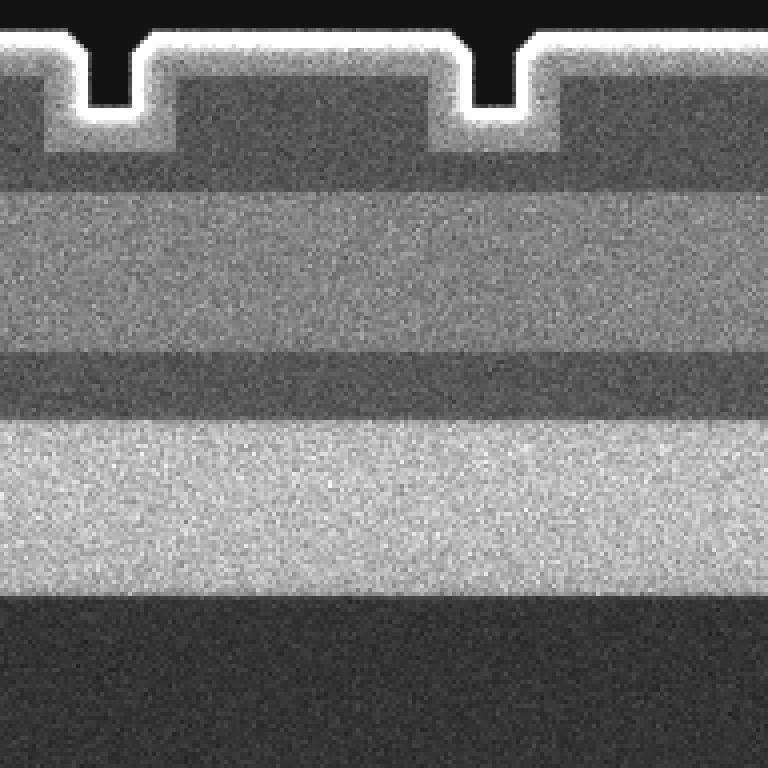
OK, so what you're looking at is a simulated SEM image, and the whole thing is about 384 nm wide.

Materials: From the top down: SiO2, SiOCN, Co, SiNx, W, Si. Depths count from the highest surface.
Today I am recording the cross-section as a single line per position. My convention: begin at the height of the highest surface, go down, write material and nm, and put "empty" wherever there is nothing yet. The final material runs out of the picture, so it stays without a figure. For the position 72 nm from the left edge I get empty 4, SiO2 56, SiOCN 20, Co 80, SiNx 34, W 88, Si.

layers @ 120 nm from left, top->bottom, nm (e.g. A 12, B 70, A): SiO2 22, SiOCN 58, Co 80, SiNx 34, W 88, Si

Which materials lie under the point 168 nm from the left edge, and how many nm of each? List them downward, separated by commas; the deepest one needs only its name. SiO2 22, SiOCN 58, Co 80, SiNx 34, W 88, Si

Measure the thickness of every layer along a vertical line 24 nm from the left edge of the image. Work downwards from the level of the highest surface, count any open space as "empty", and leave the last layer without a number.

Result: SiO2 60, SiOCN 20, Co 80, SiNx 34, W 88, Si